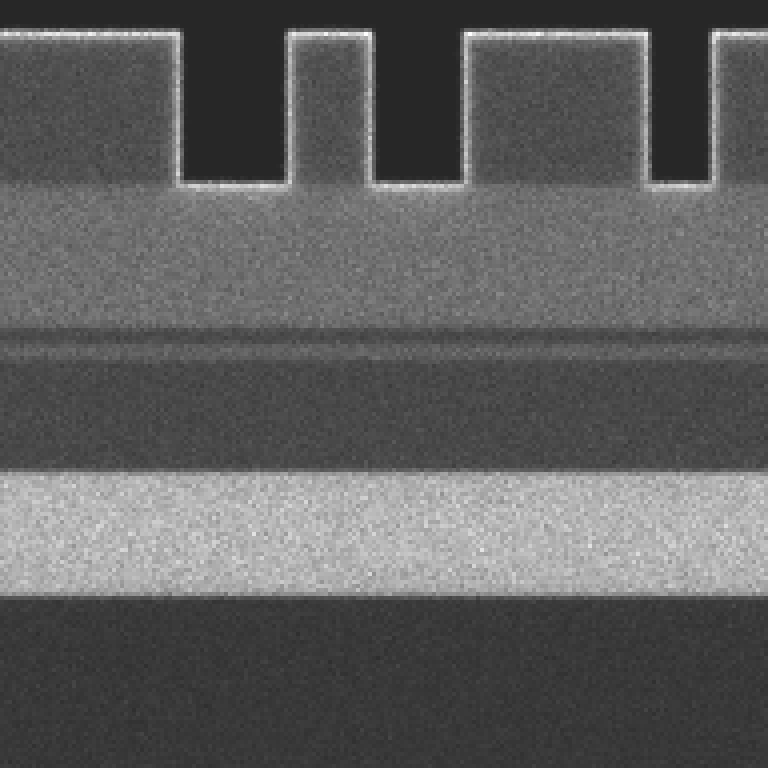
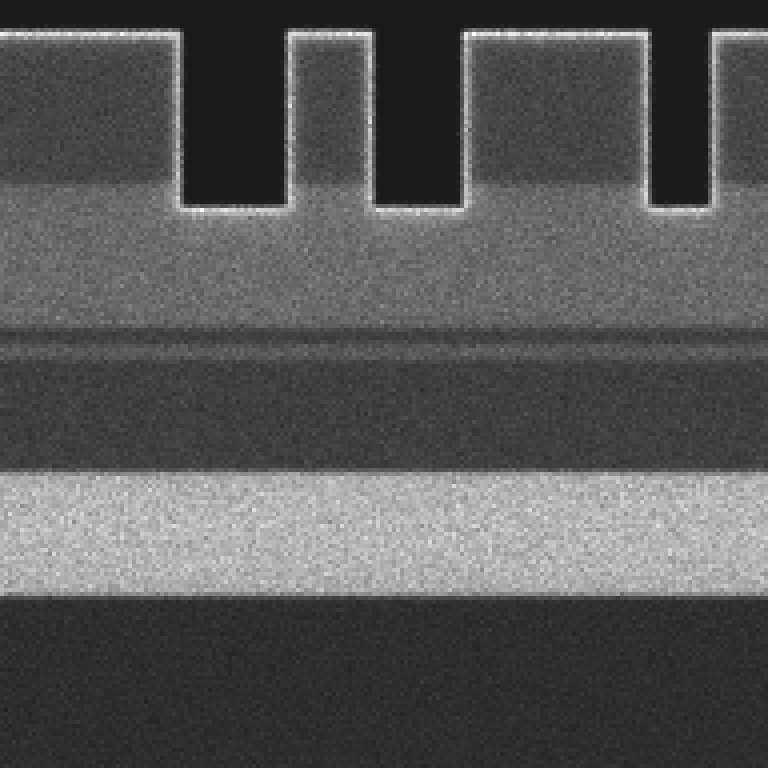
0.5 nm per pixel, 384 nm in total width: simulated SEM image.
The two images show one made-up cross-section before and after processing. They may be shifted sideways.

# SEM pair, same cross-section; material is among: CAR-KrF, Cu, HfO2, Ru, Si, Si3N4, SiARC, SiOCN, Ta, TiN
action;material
removed;Ru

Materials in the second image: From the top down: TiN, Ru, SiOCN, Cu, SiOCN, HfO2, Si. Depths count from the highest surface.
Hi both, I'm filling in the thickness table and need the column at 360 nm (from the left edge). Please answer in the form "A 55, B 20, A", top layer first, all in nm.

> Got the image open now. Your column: TiN 76, Ru 72, SiOCN 8, Cu 8, SiOCN 56, HfO2 62, Si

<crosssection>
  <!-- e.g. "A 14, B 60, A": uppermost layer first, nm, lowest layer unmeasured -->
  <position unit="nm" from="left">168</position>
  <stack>TiN 76, Ru 72, SiOCN 8, Cu 8, SiOCN 56, HfO2 62, Si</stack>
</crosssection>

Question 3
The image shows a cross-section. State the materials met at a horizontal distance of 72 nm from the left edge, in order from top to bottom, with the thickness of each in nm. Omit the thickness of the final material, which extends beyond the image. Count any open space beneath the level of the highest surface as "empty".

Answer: TiN 76, Ru 72, SiOCN 8, Cu 8, SiOCN 56, HfO2 62, Si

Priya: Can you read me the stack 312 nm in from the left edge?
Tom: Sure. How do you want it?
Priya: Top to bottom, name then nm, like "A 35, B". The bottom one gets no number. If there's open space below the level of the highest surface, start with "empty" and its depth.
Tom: TiN 76, Ru 72, SiOCN 8, Cu 8, SiOCN 56, HfO2 62, Si